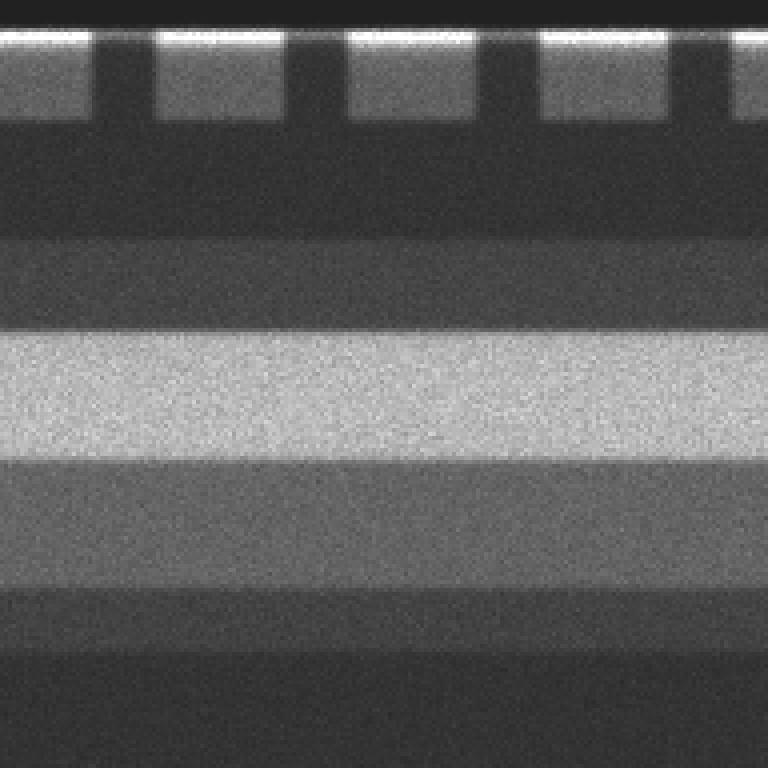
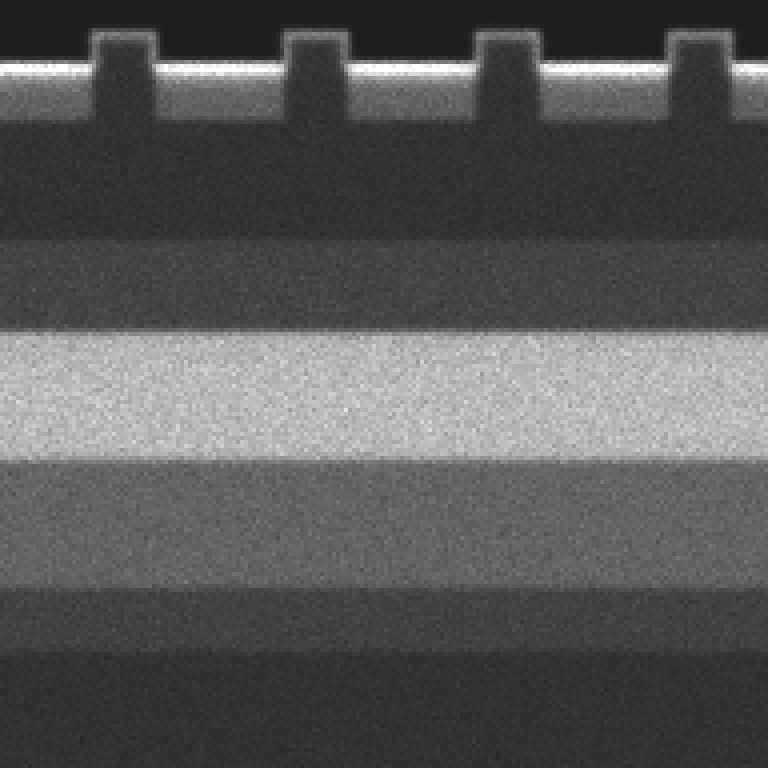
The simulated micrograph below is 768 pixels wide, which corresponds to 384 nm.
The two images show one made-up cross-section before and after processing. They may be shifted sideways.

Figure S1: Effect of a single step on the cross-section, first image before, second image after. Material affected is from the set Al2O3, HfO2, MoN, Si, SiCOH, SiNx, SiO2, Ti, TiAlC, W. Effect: removed SiO2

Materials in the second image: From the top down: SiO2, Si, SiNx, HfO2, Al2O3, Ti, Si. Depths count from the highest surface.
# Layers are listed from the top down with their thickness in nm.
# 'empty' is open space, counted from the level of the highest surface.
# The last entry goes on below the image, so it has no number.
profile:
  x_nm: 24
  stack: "empty 16, SiO2 28, Si 60, SiNx 46, HfO2 64, Al2O3 64, Ti 32, Si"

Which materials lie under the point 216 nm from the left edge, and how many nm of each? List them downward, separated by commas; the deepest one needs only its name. empty 16, SiO2 28, Si 60, SiNx 46, HfO2 64, Al2O3 64, Ti 32, Si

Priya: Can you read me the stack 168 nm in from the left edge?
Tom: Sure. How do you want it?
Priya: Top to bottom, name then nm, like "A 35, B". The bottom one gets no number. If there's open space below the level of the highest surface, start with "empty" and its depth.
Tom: Si 104, SiNx 46, HfO2 64, Al2O3 64, Ti 32, Si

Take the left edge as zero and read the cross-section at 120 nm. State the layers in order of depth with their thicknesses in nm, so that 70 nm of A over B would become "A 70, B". empty 16, SiO2 28, Si 60, SiNx 46, HfO2 64, Al2O3 64, Ti 32, Si